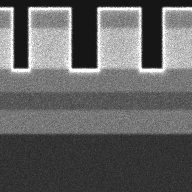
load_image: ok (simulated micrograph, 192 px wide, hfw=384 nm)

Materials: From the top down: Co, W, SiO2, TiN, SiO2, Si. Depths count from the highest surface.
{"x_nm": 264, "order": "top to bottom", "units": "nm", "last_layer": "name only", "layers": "Co 40, W 82, SiO2 46, TiN 36, SiO2 48, Si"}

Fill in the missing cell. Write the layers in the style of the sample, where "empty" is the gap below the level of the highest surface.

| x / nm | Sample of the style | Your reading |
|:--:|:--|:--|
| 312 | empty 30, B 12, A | empty 122, SiO2 46, TiN 36, SiO2 48, Si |